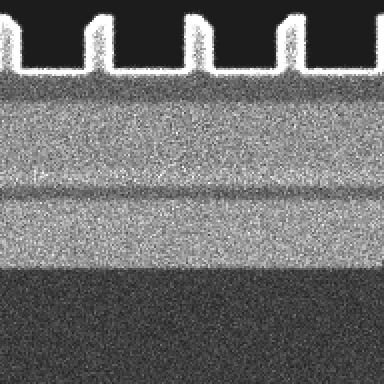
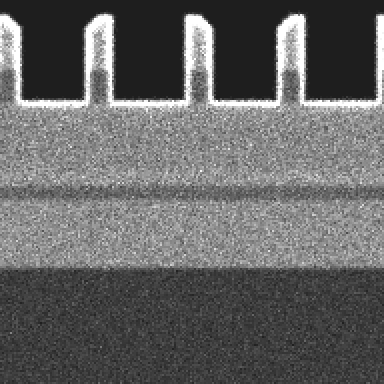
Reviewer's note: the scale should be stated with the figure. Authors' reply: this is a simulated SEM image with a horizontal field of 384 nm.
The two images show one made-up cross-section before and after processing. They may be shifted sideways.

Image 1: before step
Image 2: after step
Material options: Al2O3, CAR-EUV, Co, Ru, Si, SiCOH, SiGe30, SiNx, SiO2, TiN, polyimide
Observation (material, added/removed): SiNx, removed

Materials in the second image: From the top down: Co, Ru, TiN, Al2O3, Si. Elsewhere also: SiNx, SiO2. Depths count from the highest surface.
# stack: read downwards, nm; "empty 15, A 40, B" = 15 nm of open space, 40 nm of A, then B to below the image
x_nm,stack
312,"empty 86, Co 68, Ru 16, TiN 14, Al2O3 68, Si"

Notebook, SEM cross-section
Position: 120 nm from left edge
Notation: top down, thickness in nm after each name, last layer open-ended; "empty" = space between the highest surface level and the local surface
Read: empty 86, Co 68, Ru 16, TiN 14, Al2O3 68, Si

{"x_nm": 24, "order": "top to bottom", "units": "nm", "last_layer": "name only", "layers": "empty 86, Co 68, Ru 16, TiN 14, Al2O3 68, Si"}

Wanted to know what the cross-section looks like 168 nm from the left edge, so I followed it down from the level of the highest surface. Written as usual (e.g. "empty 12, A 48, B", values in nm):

empty 86, Co 68, Ru 16, TiN 14, Al2O3 68, Si